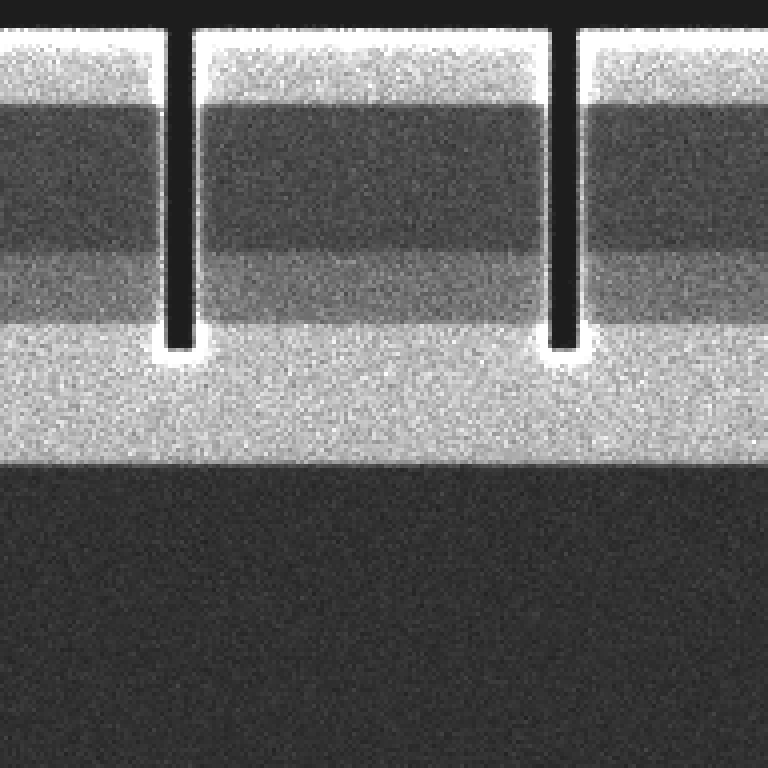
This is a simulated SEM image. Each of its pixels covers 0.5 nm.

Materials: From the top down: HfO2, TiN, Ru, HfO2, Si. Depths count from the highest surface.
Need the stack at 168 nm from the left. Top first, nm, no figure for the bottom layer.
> HfO2 36, TiN 74, Ru 36, HfO2 70, Si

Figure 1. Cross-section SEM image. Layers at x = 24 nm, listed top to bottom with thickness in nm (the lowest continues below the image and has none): HfO2 36, TiN 74, Ru 36, HfO2 70, Si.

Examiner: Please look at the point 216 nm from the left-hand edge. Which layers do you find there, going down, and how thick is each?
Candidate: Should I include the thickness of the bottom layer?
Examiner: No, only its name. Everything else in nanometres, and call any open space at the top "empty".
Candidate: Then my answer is HfO2 36, TiN 74, Ru 36, HfO2 70, Si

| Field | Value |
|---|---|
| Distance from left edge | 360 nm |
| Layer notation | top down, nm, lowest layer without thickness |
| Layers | HfO2 36, TiN 74, Ru 36, HfO2 70, Si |